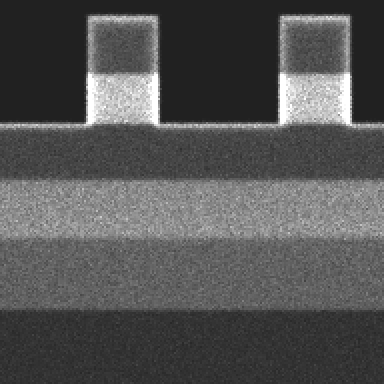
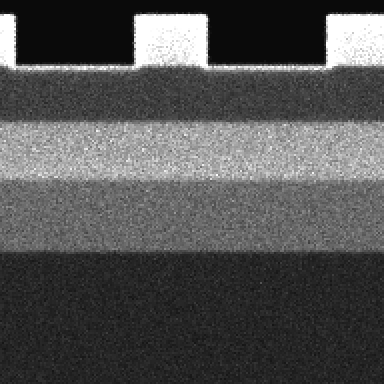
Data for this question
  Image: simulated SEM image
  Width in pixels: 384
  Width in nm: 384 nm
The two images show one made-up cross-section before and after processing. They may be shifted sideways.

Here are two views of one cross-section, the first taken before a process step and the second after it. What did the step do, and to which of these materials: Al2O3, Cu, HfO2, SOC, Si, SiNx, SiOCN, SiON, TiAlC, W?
It removed SOC.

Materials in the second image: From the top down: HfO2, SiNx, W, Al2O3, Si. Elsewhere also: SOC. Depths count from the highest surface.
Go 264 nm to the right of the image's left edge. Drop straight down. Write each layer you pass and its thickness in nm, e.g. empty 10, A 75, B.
empty 50, SiNx 56, W 58, Al2O3 72, Si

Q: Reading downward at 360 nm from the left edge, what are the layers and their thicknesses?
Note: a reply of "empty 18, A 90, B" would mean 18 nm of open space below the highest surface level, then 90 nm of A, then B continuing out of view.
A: HfO2 50, SiNx 56, W 58, Al2O3 72, Si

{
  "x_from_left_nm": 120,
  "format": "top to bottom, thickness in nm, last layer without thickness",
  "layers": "empty 50, SiNx 56, W 58, Al2O3 72, Si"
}